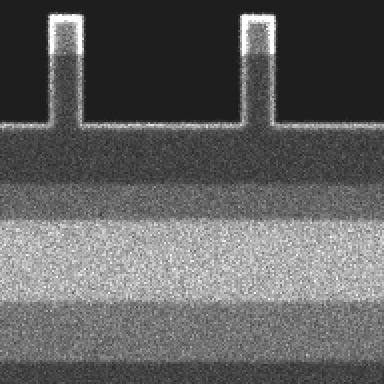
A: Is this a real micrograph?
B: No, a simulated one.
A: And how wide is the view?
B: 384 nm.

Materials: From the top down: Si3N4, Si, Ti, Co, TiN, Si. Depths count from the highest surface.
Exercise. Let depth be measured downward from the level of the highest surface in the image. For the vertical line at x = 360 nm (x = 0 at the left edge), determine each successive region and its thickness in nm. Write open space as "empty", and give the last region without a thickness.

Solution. empty 108, Si 60, Ti 36, Co 82, TiN 60, Si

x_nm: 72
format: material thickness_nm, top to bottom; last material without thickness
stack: Si3N4 38, Si 130, Ti 36, Co 82, TiN 60, Si